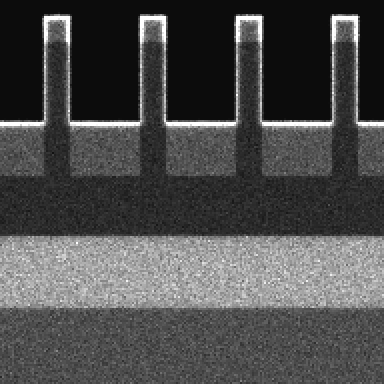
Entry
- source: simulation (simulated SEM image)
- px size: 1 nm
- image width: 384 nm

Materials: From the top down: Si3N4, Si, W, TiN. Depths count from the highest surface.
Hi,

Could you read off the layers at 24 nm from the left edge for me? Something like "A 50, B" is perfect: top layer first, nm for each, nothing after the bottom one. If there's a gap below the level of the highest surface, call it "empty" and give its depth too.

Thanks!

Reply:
empty 106, Si3N4 54, Si 60, W 72, TiN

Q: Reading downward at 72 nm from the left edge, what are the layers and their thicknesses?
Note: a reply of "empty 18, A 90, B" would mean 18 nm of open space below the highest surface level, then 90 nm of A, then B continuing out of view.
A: empty 106, Si3N4 54, Si 60, W 72, TiN